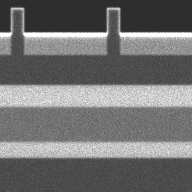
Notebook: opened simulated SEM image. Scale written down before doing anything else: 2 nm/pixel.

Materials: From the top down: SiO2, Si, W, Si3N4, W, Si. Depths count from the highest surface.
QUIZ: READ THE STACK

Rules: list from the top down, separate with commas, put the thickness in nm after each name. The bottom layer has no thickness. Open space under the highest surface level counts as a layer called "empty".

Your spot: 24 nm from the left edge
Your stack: Si 154, W 44, Si3N4 70, W 32, Si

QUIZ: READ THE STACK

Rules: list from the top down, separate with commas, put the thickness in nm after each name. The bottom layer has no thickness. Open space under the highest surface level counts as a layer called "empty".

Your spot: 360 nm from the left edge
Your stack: empty 50, SiO2 44, Si 60, W 44, Si3N4 70, W 32, Si